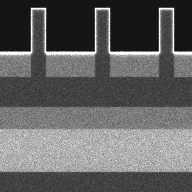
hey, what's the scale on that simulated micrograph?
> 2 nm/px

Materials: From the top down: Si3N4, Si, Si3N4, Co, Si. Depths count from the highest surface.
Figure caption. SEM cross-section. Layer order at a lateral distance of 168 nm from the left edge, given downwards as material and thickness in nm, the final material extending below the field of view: empty 88, Si3N4 50, Si 60, Si3N4 44, Co 86, Si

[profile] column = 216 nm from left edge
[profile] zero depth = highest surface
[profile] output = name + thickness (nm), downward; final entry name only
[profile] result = Si 198, Si3N4 44, Co 86, Si